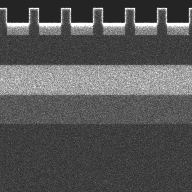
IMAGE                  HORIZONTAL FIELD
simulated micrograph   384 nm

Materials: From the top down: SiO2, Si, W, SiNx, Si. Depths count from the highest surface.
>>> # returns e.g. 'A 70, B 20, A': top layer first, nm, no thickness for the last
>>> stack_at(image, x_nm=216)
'empty 30, SiO2 24, Si 60, W 60, SiNx 58, Si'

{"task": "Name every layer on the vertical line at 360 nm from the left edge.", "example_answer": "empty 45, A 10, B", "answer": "empty 30, SiO2 24, Si 60, W 60, SiNx 58, Si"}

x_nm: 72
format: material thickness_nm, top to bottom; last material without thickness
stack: Si 114, W 60, SiNx 58, Si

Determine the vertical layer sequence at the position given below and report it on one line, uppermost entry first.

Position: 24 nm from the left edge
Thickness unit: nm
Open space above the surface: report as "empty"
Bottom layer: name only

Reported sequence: empty 30, SiO2 24, Si 60, W 60, SiNx 58, Si